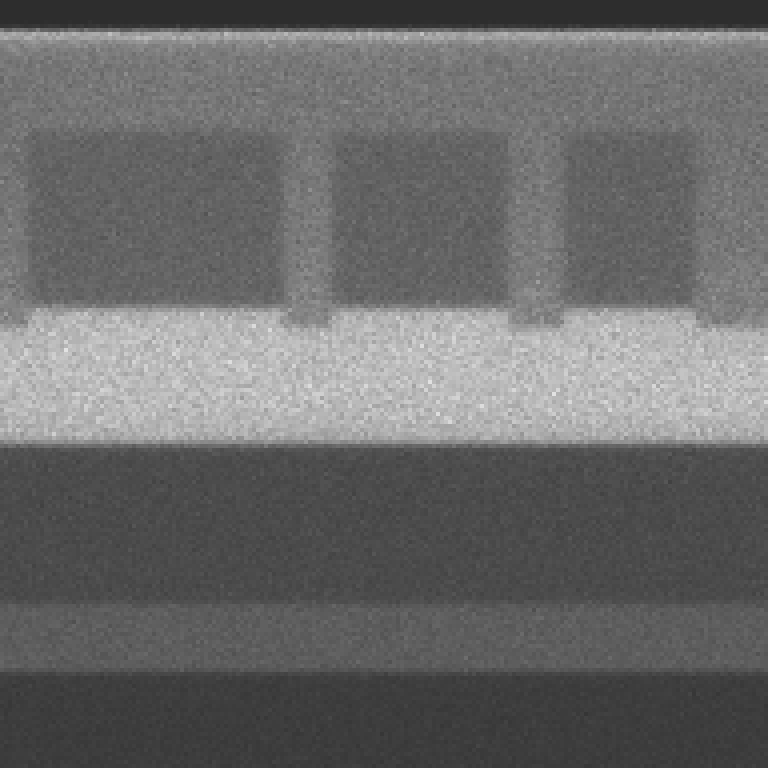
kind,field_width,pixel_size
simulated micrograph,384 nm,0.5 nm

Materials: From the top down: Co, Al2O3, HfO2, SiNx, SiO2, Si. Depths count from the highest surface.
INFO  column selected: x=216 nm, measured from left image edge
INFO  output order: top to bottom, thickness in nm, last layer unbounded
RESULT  Co 50, Al2O3 88, HfO2 68, SiNx 80, SiO2 34, Si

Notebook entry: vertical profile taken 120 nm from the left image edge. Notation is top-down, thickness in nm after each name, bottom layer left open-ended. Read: Co 50, Al2O3 88, HfO2 68, SiNx 80, SiO2 34, Si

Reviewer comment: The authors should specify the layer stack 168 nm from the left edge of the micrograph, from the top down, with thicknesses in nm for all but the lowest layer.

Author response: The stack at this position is Co 50, Al2O3 88, HfO2 68, SiNx 80, SiO2 34, Si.